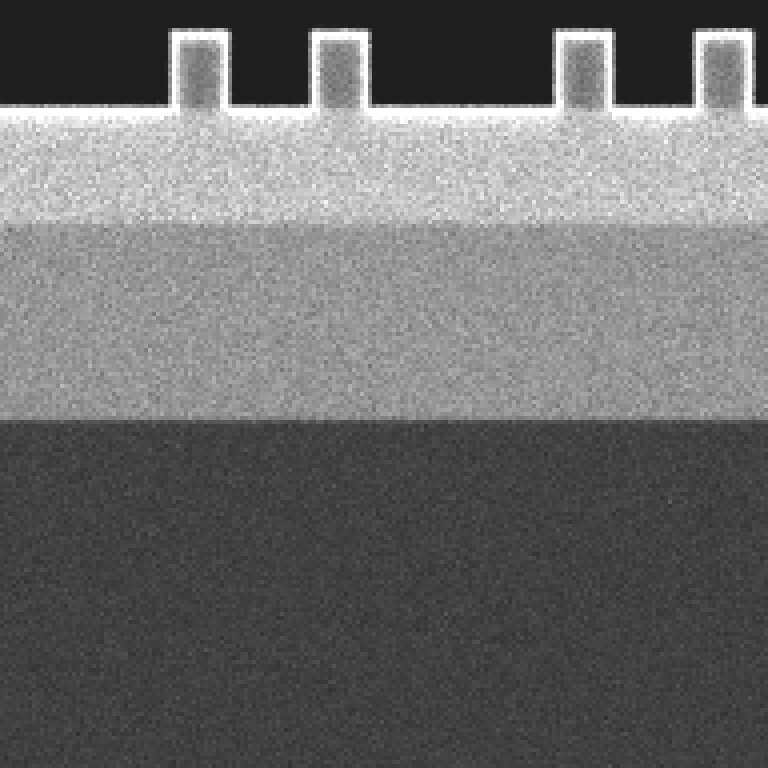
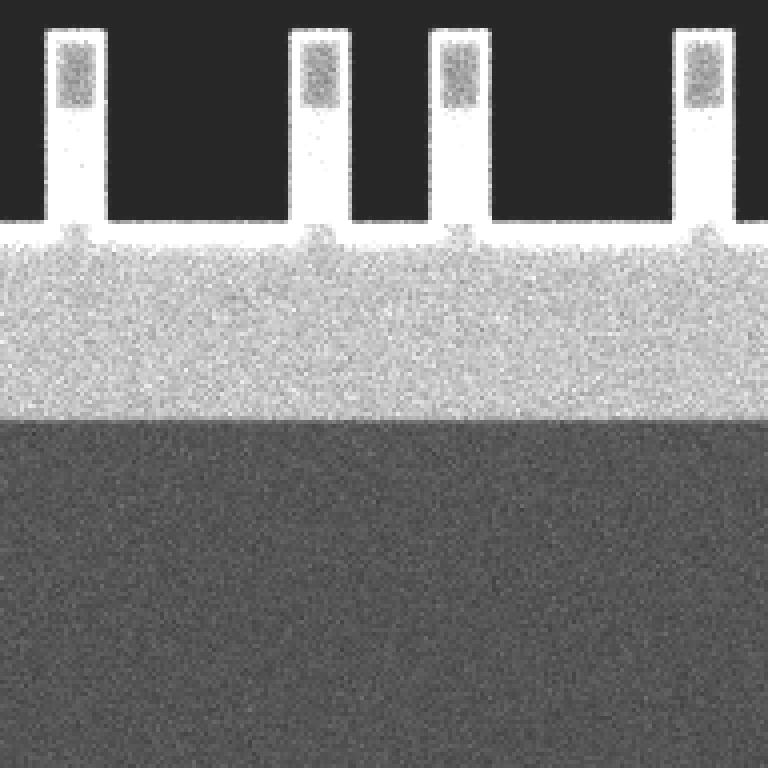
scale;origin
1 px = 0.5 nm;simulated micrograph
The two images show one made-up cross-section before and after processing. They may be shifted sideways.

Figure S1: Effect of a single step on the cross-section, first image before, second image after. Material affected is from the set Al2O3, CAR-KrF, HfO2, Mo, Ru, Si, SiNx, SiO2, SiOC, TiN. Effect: removed Ru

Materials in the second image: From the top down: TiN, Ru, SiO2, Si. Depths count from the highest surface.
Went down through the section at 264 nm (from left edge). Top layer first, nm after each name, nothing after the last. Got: empty 96, SiO2 98, Si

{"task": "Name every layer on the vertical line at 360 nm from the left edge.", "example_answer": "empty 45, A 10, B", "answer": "TiN 38, Ru 58, SiO2 98, Si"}